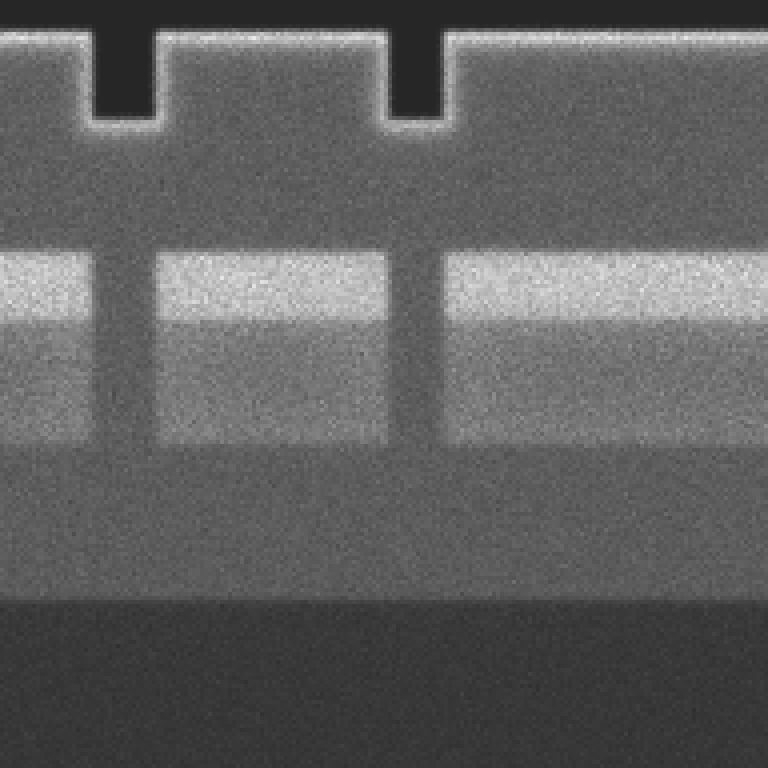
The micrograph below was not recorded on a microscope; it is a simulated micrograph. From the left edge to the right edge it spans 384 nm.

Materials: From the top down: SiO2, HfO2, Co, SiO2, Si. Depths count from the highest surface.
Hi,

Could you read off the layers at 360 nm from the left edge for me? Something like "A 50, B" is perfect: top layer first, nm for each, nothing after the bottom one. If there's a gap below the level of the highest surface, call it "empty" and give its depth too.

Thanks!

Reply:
SiO2 110, HfO2 34, Co 62, SiO2 78, Si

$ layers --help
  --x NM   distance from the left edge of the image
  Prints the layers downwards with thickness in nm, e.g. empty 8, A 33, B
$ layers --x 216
empty 44, SiO2 240, Si